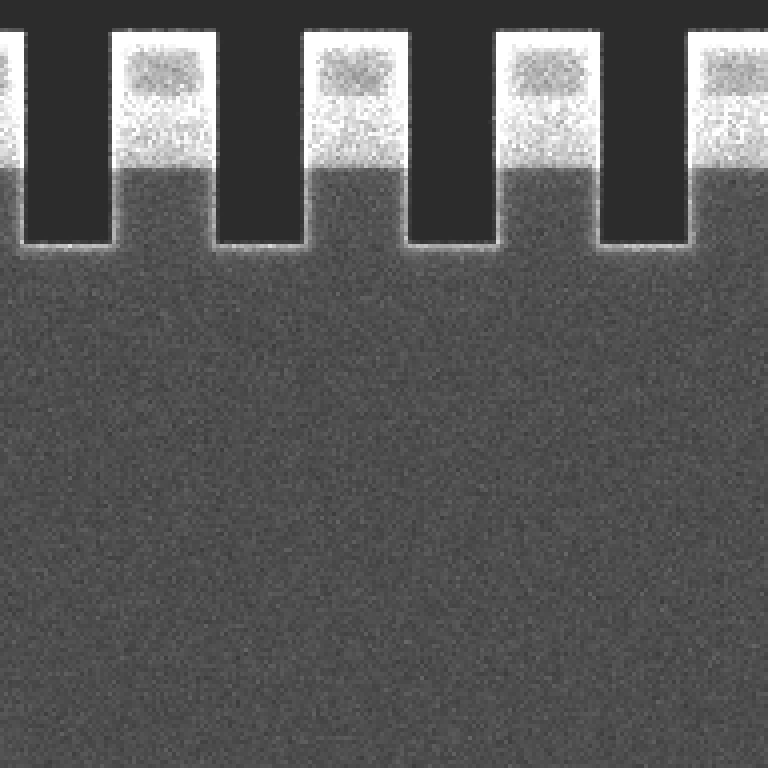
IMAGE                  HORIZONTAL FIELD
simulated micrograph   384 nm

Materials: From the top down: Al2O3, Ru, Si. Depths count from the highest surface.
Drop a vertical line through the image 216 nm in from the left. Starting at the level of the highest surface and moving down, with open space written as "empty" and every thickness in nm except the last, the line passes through empty 106, Si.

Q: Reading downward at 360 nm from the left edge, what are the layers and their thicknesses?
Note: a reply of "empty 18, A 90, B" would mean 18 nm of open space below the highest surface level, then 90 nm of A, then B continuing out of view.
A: Al2O3 32, Ru 36, Si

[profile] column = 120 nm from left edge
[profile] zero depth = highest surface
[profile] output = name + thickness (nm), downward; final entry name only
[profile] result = empty 106, Si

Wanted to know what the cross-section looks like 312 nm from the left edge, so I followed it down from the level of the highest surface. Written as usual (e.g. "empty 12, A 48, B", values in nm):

empty 106, Si